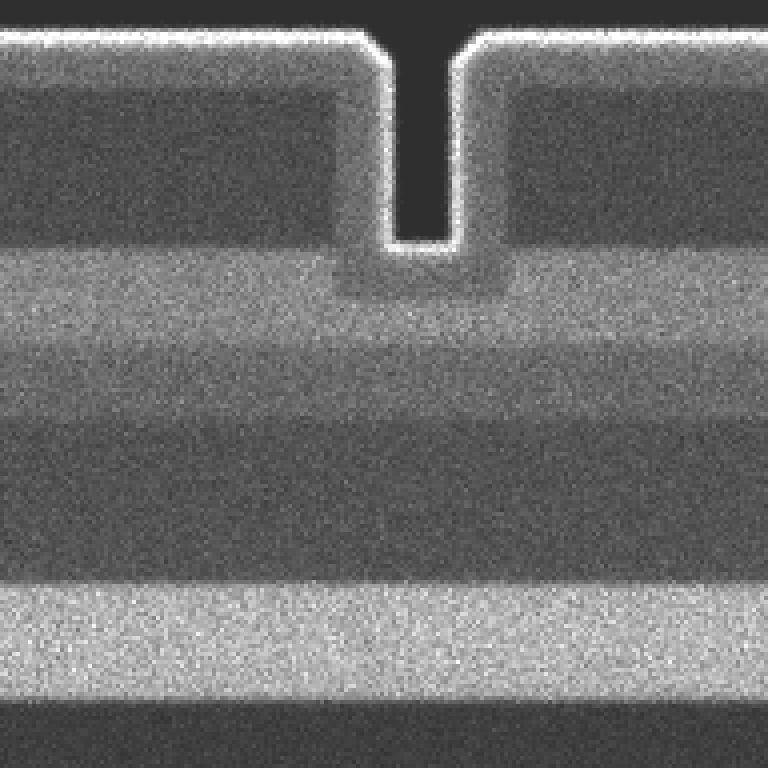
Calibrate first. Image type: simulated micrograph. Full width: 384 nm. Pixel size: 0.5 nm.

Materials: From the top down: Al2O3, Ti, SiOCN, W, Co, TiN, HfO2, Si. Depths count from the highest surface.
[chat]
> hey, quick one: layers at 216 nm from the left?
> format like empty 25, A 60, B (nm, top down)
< empty 106, Al2O3 28, W 22, Co 38, TiN 82, HfO2 58, Si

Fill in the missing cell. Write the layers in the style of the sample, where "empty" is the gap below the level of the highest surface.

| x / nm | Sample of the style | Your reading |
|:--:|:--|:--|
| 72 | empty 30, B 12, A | Al2O3 28, Ti 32, SiOCN 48, W 48, Co 38, TiN 82, HfO2 58, Si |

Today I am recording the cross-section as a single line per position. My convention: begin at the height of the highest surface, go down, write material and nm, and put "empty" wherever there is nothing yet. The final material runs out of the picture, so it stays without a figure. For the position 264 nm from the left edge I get Al2O3 28, Ti 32, SiOCN 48, W 48, Co 38, TiN 82, HfO2 58, Si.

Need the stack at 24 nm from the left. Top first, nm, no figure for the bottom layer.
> Al2O3 28, Ti 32, SiOCN 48, W 48, Co 38, TiN 82, HfO2 58, Si